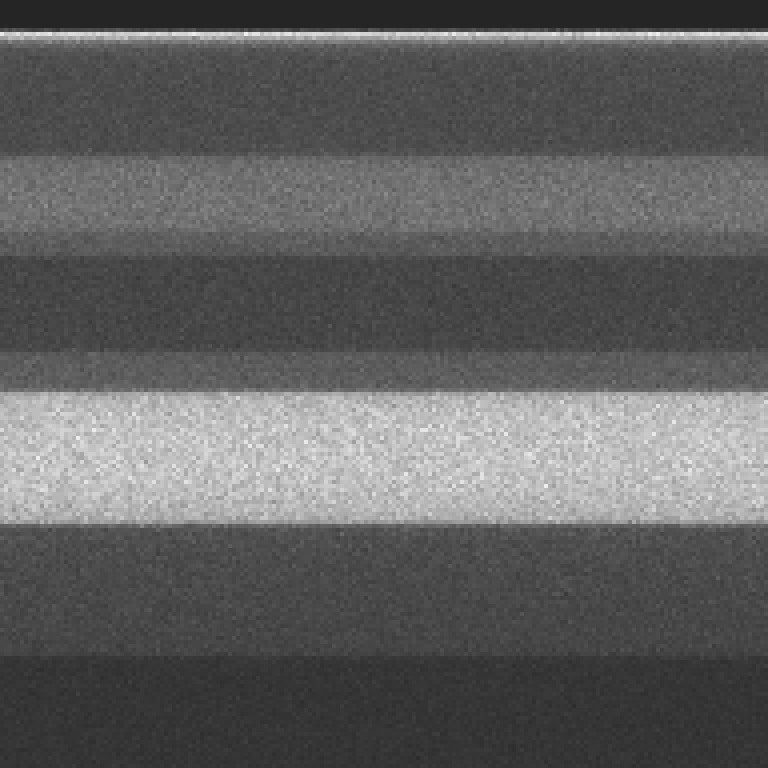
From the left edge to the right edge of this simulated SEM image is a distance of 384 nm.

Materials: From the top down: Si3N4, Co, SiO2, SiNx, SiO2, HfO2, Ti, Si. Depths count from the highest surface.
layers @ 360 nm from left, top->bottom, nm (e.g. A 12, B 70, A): Si3N4 62, Co 38, SiO2 12, SiNx 48, SiO2 20, HfO2 66, Ti 66, Si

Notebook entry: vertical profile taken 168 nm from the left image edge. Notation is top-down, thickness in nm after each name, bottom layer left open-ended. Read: Si3N4 62, Co 38, SiO2 12, SiNx 48, SiO2 20, HfO2 66, Ti 66, Si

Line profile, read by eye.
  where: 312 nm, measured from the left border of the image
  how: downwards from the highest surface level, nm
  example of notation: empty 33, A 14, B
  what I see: Si3N4 62, Co 38, SiO2 12, SiNx 48, SiO2 20, HfO2 66, Ti 66, Si